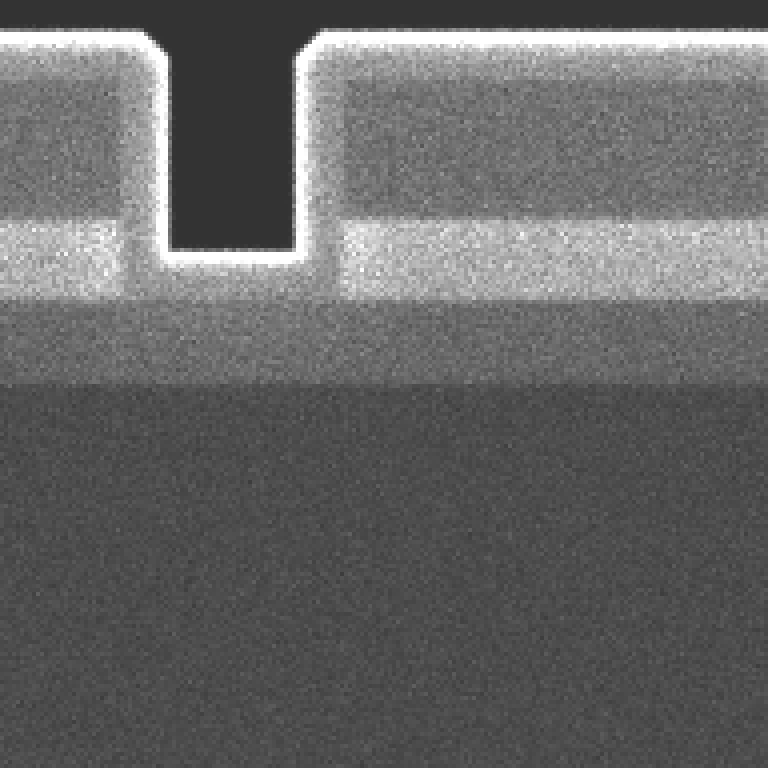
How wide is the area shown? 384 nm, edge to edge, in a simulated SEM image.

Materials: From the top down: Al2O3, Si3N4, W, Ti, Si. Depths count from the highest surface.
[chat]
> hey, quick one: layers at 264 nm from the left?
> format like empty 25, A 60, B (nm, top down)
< Al2O3 24, Si3N4 70, W 40, Ti 42, Si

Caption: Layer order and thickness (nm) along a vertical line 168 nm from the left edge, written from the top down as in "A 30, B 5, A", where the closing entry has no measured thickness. Al2O3 134, Ti 42, Si